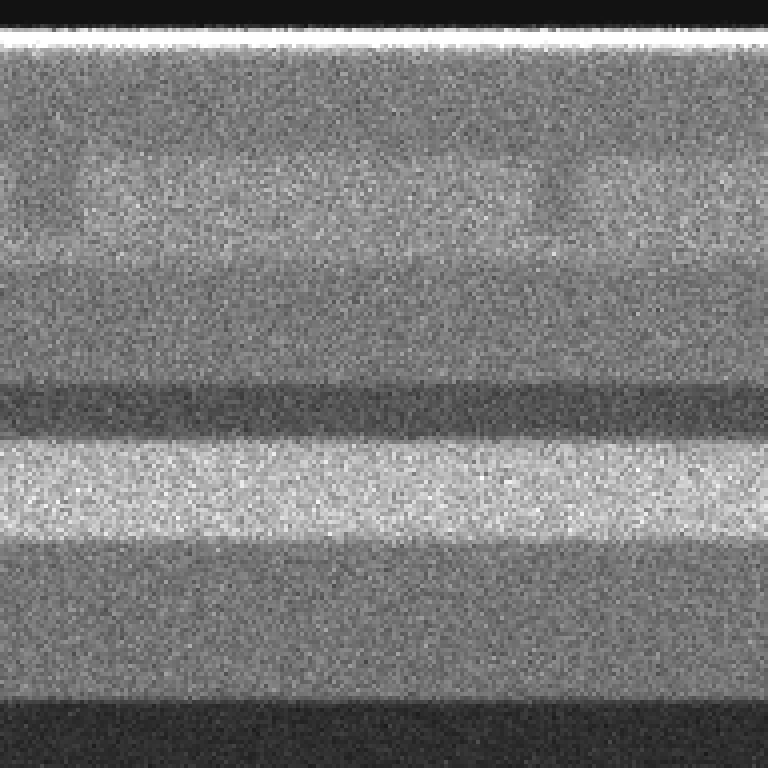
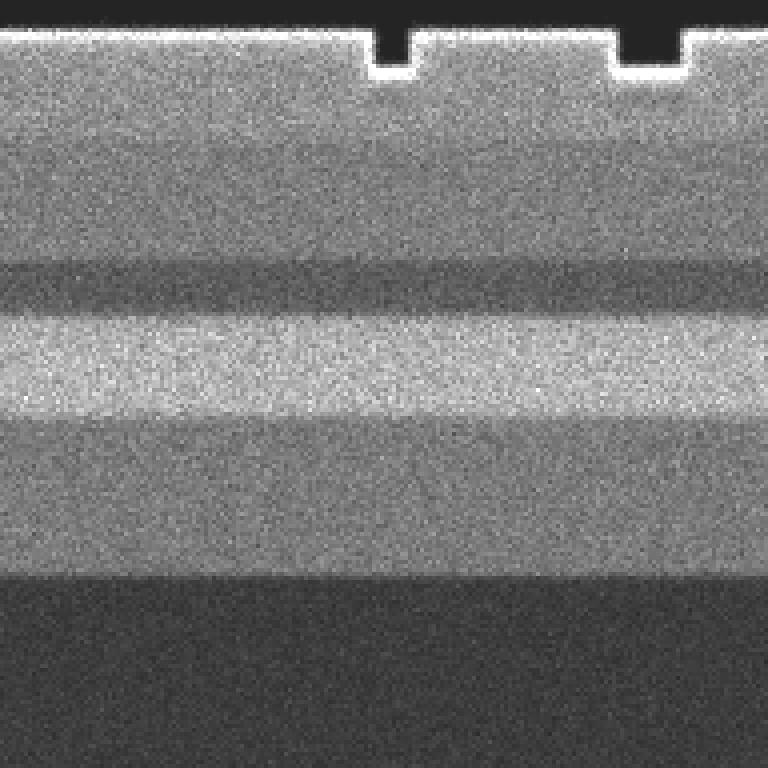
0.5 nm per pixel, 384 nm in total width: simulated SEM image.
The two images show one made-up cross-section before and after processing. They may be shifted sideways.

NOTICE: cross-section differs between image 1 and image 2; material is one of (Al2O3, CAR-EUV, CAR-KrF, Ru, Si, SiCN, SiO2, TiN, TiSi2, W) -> removed: Al2O3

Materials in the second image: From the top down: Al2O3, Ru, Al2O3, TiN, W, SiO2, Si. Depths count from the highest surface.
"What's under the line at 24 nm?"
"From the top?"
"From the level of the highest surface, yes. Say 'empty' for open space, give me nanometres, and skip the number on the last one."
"Ru 54, Al2O3 60, TiN 28, W 50, SiO2 80, Si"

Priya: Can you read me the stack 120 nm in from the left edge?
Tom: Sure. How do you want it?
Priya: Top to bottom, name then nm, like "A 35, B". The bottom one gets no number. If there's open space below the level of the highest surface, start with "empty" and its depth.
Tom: Ru 54, Al2O3 60, TiN 28, W 50, SiO2 80, Si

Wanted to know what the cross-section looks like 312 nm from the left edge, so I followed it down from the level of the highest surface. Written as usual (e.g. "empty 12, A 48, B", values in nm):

empty 18, Al2O3 20, Ru 16, Al2O3 60, TiN 28, W 50, SiO2 80, Si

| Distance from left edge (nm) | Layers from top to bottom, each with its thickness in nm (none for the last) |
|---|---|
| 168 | Ru 54, Al2O3 60, TiN 28, W 50, SiO2 80, Si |